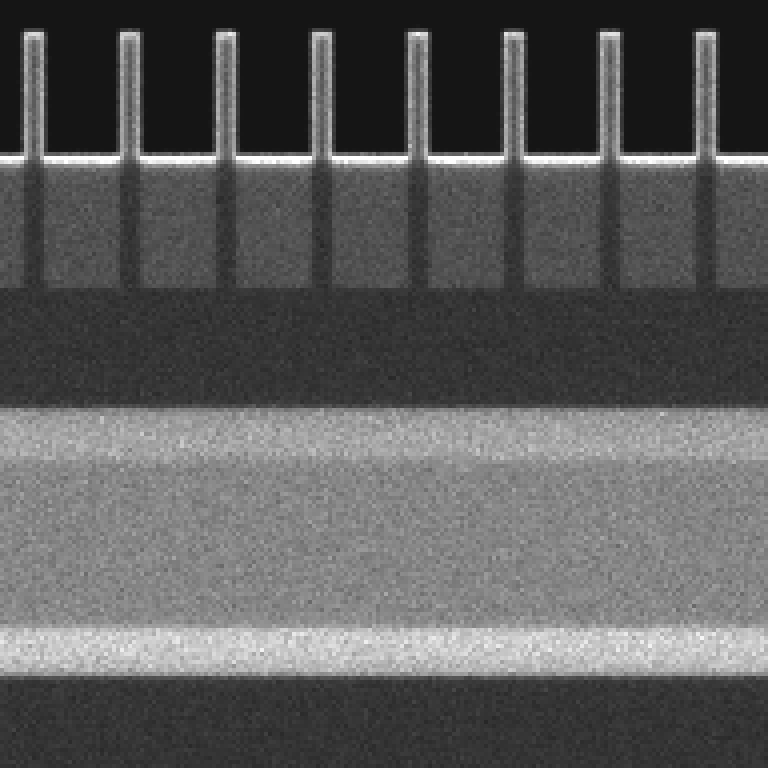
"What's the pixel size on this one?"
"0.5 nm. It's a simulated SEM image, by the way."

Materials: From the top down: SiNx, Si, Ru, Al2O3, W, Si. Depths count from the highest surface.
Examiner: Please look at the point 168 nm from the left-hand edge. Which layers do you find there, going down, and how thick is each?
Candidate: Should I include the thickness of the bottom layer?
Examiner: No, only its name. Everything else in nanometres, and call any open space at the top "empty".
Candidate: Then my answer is empty 62, SiNx 66, Si 60, Ru 26, Al2O3 84, W 24, Si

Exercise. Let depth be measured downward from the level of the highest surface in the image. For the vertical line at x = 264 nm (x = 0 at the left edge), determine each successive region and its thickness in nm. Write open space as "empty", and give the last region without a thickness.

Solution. empty 62, SiNx 66, Si 60, Ru 26, Al2O3 84, W 24, Si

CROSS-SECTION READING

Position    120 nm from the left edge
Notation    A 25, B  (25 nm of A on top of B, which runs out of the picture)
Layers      empty 62, SiNx 66, Si 60, Ru 26, Al2O3 84, W 24, Si